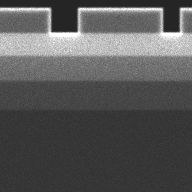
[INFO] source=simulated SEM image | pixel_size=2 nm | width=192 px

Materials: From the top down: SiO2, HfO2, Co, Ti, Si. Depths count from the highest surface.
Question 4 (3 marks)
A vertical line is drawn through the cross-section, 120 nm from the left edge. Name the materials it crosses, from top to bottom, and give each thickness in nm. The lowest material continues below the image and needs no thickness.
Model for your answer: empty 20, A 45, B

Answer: empty 50, HfO2 46, Co 50, Ti 58, Si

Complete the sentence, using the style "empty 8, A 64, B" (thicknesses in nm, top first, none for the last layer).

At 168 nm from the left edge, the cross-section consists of SiO2 50, HfO2 46, Co 50, Ti 58, Si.